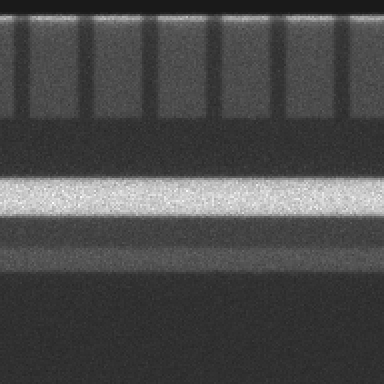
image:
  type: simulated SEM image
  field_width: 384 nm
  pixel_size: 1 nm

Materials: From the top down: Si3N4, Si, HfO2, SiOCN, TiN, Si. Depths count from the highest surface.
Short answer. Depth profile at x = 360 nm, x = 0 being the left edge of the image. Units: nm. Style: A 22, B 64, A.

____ Si3N4 102, Si 60, HfO2 38, SiOCN 32, TiN 24, Si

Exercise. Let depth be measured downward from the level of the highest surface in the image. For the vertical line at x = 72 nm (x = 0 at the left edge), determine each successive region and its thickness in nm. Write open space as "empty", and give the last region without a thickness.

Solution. Si3N4 102, Si 60, HfO2 38, SiOCN 32, TiN 24, Si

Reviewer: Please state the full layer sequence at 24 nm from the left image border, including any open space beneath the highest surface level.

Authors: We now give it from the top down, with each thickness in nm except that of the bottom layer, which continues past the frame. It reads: Si 162, HfO2 38, SiOCN 32, TiN 24, Si